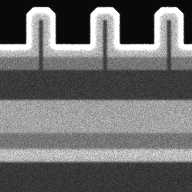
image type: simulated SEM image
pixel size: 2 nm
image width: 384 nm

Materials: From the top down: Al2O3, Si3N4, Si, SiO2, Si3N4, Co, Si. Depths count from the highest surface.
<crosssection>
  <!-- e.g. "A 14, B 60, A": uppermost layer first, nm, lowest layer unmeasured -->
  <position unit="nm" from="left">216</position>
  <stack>Al2O3 98, Si3N4 26, Si 60, SiO2 66, Si3N4 32, Co 26, Si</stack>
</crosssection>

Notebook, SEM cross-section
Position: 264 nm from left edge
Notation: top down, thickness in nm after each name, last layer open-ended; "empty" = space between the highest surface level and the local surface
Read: empty 74, Al2O3 24, Si3N4 26, Si 60, SiO2 66, Si3N4 32, Co 26, Si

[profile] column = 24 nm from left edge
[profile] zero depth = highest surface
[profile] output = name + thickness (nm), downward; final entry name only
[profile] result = empty 74, Al2O3 24, Si3N4 26, Si 60, SiO2 66, Si3N4 32, Co 26, Si